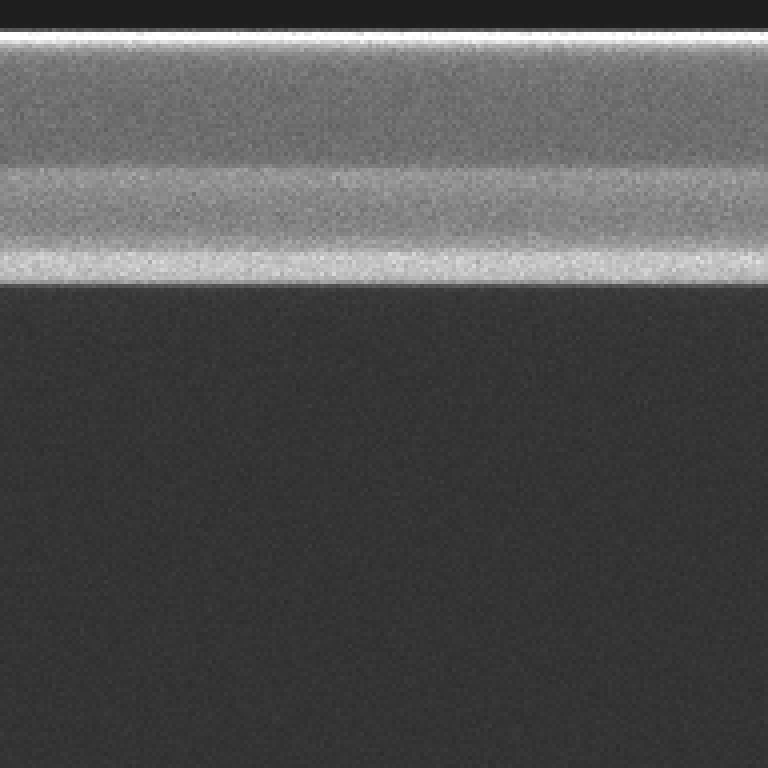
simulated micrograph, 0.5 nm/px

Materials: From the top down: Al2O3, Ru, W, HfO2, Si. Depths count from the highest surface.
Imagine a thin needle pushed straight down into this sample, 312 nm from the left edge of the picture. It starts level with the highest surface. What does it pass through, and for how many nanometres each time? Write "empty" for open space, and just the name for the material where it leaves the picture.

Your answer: Al2O3 68, Ru 34, W 8, HfO2 16, Si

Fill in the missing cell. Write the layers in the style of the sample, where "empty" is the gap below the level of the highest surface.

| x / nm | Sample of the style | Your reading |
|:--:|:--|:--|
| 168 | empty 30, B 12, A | Al2O3 68, Ru 34, W 8, HfO2 16, Si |